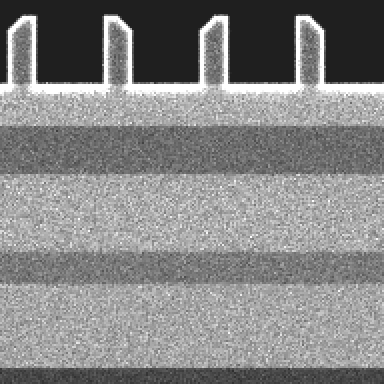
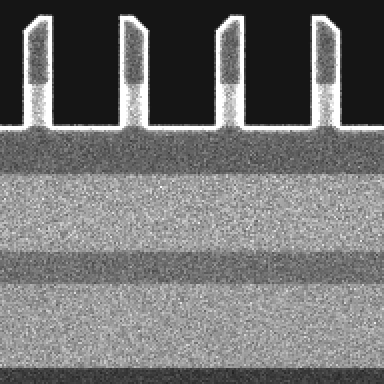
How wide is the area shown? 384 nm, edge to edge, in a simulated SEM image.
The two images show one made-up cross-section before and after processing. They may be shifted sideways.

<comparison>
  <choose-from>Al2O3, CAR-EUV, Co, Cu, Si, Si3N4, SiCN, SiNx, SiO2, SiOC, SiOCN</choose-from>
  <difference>Al2O3 removed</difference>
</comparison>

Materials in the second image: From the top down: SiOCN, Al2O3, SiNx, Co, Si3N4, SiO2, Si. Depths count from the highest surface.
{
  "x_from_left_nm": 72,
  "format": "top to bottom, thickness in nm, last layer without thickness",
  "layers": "empty 110, SiNx 48, Co 78, Si3N4 32, SiO2 84, Si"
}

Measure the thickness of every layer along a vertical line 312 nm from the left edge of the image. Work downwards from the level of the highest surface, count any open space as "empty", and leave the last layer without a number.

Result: SiOCN 68, Al2O3 42, SiNx 48, Co 78, Si3N4 32, SiO2 84, Si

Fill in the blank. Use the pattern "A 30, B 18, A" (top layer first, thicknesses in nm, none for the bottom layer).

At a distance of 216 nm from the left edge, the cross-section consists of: empty 14, SiOCN 54, Al2O3 42, SiNx 48, Co 78, Si3N4 32, SiO2 84, Si